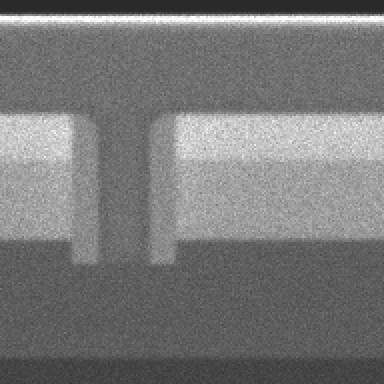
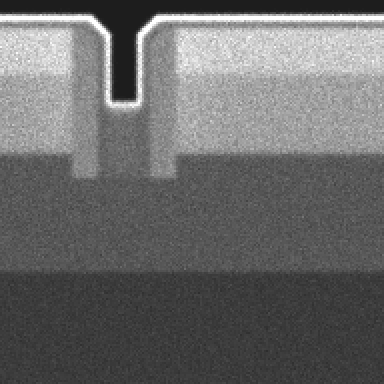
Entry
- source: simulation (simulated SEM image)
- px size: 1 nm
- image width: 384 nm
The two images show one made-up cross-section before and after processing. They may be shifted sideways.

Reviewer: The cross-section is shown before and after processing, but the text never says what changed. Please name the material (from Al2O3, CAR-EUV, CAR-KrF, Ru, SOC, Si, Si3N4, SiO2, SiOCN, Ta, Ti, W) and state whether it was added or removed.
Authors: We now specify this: SOC, removed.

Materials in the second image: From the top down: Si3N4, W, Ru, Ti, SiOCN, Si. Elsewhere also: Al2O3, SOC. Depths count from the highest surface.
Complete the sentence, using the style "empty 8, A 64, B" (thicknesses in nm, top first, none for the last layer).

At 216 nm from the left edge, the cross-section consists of Si3N4 12, W 46, Ru 80, Ti 86, SiOCN 32, Si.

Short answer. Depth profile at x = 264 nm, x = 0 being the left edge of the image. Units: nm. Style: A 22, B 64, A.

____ Si3N4 12, W 46, Ru 80, Ti 86, SiOCN 32, Si